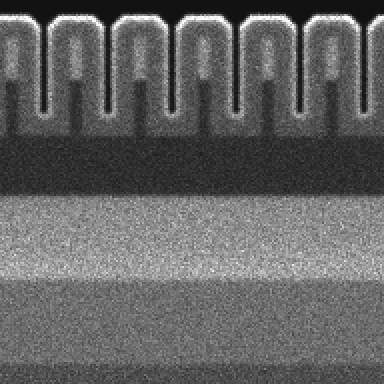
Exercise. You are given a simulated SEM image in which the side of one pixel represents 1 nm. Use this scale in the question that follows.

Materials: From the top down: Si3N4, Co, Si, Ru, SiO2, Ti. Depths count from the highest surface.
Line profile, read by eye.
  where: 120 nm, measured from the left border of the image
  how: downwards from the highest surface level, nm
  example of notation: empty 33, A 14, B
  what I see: empty 2, Si3N4 118, Si 60, Ru 84, SiO2 84, Ti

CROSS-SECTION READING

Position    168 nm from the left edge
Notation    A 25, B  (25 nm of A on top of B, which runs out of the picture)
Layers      empty 98, Si3N4 22, Si 60, Ru 84, SiO2 84, Ti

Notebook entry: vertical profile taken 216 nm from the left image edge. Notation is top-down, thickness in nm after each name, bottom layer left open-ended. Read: Si3N4 120, Si 60, Ru 84, SiO2 84, Ti